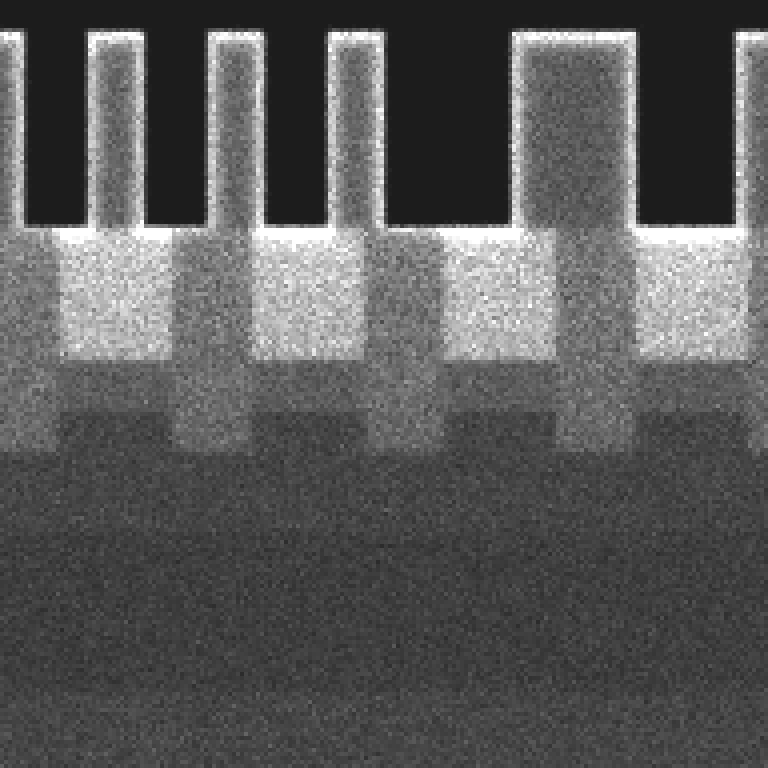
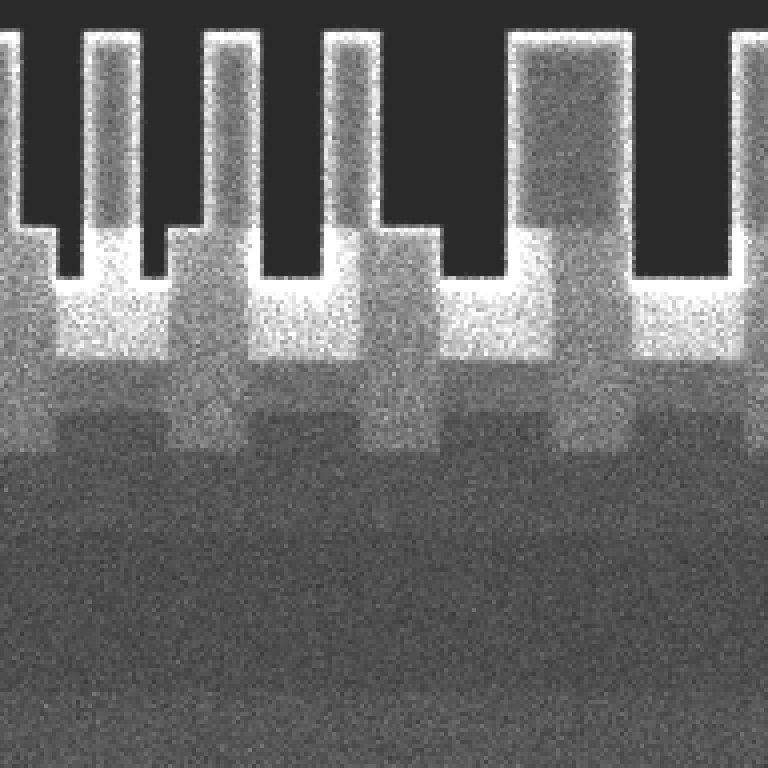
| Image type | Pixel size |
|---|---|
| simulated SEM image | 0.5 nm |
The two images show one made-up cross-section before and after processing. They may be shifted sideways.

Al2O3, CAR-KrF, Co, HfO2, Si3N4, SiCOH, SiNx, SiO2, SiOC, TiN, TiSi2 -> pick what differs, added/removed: HfO2 removed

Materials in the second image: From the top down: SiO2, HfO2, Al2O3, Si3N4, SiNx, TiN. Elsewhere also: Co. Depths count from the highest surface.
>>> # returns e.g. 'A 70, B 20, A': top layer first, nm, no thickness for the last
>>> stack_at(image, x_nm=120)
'SiO2 98, Co 112, Si3N4 40, SiNx 80, TiN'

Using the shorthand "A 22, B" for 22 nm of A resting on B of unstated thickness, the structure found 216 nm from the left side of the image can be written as empty 98, Co 112, Si3N4 40, SiNx 80, TiN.